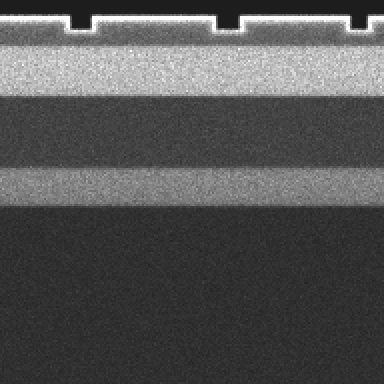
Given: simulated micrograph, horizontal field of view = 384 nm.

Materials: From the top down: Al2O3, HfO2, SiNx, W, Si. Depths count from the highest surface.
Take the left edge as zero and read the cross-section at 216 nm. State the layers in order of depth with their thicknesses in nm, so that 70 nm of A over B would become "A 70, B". empty 14, Al2O3 16, HfO2 50, SiNx 72, W 38, Si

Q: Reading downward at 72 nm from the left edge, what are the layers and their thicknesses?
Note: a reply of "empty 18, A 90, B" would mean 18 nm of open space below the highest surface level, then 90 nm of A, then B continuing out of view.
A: empty 14, Al2O3 16, HfO2 50, SiNx 72, W 38, Si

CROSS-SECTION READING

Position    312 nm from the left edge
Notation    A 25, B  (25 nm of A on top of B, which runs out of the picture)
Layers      Al2O3 30, HfO2 50, SiNx 72, W 38, Si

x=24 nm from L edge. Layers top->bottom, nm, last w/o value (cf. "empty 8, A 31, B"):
Al2O3 30, HfO2 50, SiNx 72, W 38, Si